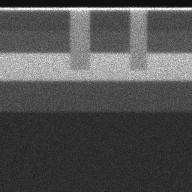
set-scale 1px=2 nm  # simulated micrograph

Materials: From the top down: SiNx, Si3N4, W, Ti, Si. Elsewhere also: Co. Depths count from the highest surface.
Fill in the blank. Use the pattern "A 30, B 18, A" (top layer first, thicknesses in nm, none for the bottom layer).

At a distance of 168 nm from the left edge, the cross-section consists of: Co 124, W 22, Ti 62, Si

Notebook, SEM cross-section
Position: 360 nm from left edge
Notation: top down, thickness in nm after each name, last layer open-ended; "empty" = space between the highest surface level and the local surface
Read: SiNx 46, Si3N4 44, W 56, Ti 62, Si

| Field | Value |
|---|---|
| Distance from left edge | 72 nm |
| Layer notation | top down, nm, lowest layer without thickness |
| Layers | SiNx 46, Si3N4 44, W 56, Ti 62, Si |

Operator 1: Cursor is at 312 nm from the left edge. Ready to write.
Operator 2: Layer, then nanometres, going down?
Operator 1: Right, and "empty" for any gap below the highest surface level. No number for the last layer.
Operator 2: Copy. SiNx 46, Si3N4 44, W 56, Ti 62, Si